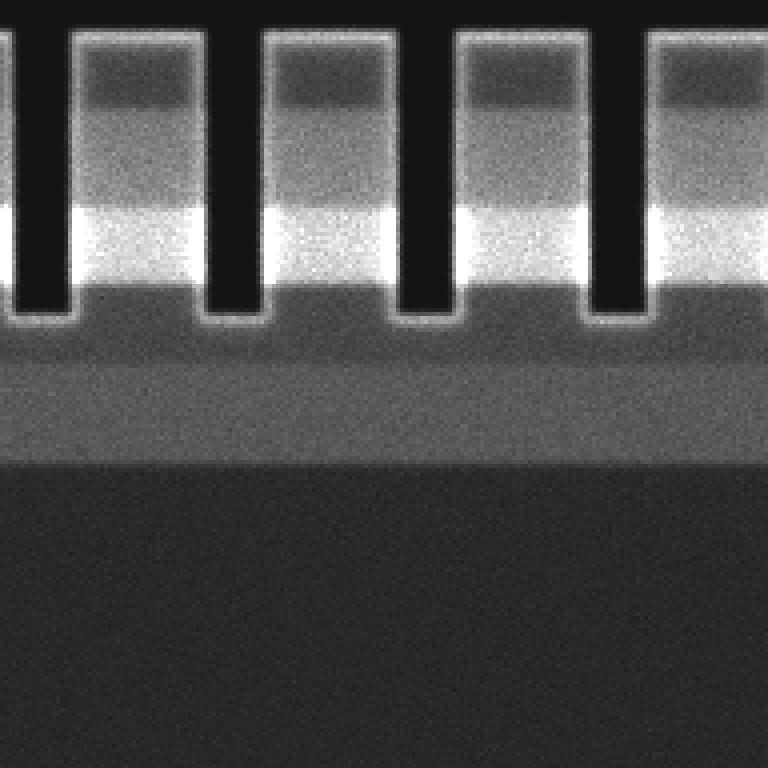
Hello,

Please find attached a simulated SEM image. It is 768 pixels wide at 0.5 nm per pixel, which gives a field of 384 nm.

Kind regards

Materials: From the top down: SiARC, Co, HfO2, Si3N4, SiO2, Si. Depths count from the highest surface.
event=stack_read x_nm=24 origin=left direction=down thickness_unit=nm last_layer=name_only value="empty 142, Si3N4 24, SiO2 50, Si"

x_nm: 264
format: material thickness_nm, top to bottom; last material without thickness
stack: SiARC 38, Co 50, HfO2 38, Si3N4 40, SiO2 50, Si